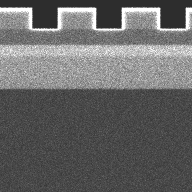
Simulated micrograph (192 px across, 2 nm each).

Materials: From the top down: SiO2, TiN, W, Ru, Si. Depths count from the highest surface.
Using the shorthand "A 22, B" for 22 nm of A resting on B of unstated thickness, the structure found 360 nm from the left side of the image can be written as empty 42, TiN 32, W 22, Ru 66, Si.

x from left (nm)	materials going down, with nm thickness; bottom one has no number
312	SiO2 42, TiN 32, W 22, Ru 66, Si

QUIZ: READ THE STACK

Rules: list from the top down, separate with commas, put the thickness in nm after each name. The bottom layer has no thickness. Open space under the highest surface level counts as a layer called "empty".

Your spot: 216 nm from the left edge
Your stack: empty 42, TiN 32, W 22, Ru 66, Si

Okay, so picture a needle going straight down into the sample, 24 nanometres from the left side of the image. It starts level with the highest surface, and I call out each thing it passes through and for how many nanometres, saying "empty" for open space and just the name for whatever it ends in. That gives SiO2 42, TiN 32, W 22, Ru 66, Si